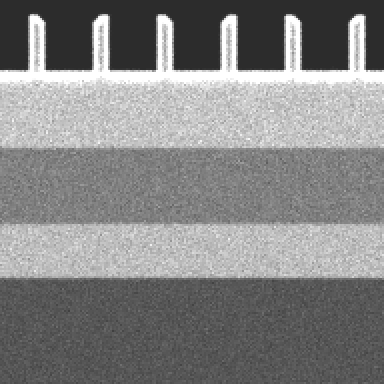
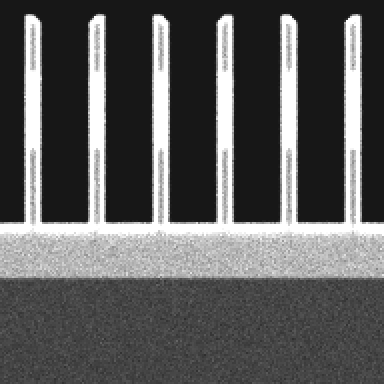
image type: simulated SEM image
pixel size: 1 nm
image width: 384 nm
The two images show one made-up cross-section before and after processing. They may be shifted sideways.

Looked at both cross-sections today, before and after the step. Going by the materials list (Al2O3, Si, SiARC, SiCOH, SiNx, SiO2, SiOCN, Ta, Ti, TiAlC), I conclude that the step removed Al2O3 and SiNx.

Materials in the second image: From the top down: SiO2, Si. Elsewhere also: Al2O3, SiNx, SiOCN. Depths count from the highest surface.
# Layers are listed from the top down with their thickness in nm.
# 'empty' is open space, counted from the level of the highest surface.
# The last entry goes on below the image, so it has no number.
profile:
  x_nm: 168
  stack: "empty 208, SiO2 54, Si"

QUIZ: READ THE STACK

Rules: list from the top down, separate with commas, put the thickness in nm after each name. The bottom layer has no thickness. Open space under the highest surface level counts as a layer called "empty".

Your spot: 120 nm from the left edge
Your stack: empty 208, SiO2 54, Si